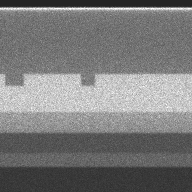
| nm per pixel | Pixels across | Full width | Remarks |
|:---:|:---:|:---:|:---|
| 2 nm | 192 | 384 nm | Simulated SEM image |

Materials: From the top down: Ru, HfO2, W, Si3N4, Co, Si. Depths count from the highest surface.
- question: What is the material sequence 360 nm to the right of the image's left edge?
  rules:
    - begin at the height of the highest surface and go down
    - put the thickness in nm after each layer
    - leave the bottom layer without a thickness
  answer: Ru 132, HfO2 76, W 42, Si3N4 40, Co 28, Si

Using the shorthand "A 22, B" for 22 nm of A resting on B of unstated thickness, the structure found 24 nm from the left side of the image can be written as Ru 156, HfO2 52, W 42, Si3N4 40, Co 28, Si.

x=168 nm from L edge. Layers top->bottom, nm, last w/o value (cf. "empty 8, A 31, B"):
Ru 156, HfO2 52, W 42, Si3N4 40, Co 28, Si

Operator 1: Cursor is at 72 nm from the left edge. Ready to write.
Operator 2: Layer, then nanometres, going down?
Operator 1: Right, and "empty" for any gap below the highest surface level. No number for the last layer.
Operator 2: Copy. Ru 132, HfO2 76, W 42, Si3N4 40, Co 28, Si